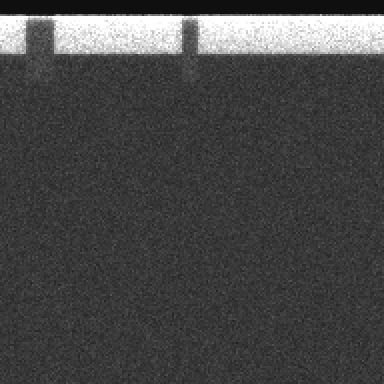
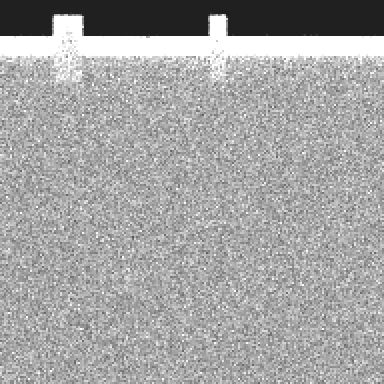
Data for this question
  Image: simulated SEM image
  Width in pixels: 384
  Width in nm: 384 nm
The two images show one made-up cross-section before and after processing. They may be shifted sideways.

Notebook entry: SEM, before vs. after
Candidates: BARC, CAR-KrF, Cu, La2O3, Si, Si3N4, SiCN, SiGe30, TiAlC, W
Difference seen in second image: W removed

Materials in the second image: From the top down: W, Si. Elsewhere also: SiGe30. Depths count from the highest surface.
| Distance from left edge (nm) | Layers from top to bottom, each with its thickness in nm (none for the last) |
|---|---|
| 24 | empty 22, W 16, Si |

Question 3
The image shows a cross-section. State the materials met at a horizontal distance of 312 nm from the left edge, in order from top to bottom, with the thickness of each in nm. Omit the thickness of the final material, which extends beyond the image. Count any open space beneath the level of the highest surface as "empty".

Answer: empty 22, W 16, Si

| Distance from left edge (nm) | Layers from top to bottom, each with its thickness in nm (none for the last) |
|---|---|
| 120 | empty 22, W 16, Si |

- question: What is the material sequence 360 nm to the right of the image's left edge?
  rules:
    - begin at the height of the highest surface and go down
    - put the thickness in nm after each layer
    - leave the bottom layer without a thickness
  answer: empty 22, W 16, Si